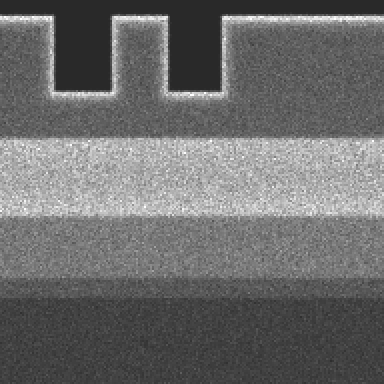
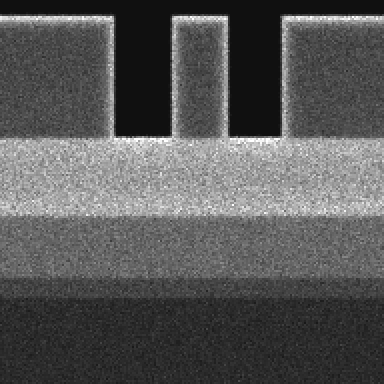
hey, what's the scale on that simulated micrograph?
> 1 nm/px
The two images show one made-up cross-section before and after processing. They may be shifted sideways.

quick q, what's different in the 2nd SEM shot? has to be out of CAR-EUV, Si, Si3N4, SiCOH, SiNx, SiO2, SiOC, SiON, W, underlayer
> underlayer removed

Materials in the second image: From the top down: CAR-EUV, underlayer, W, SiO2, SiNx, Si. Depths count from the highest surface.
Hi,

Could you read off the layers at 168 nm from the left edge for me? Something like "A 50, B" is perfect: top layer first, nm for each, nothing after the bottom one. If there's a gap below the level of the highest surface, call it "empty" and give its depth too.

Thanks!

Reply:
empty 122, W 78, SiO2 62, SiNx 20, Si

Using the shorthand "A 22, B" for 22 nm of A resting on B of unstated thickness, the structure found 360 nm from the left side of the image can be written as CAR-EUV 76, underlayer 46, W 78, SiO2 62, SiNx 20, Si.